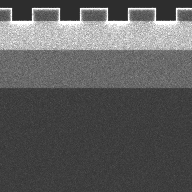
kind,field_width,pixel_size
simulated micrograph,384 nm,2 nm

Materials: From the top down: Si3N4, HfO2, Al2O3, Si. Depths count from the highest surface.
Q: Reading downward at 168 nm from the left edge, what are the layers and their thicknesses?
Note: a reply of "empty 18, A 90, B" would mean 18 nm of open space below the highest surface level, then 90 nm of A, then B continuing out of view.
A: Si3N4 26, HfO2 58, Al2O3 76, Si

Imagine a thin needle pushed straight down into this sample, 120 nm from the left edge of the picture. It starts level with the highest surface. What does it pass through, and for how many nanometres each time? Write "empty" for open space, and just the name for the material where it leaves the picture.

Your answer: empty 26, HfO2 58, Al2O3 76, Si